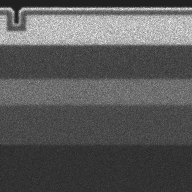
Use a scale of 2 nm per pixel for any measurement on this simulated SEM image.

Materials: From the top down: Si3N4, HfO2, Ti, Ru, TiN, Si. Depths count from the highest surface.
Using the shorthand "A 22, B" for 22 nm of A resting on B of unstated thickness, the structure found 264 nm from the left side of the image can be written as Si3N4 14, HfO2 60, Ti 68, Ru 52, TiN 80, Si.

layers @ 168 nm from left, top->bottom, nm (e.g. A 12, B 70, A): Si3N4 14, HfO2 60, Ti 68, Ru 52, TiN 80, Si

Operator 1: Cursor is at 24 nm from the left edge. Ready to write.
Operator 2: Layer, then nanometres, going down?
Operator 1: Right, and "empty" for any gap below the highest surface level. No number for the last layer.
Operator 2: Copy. empty 4, Si3N4 42, HfO2 28, Ti 68, Ru 52, TiN 80, Si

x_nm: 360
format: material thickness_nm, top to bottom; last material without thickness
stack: Si3N4 14, HfO2 60, Ti 68, Ru 52, TiN 80, Si